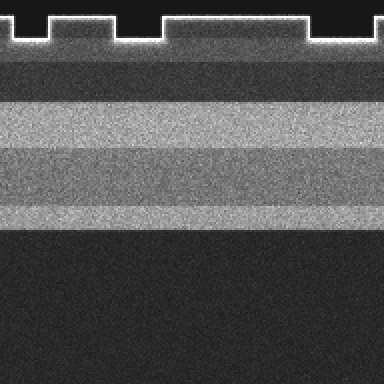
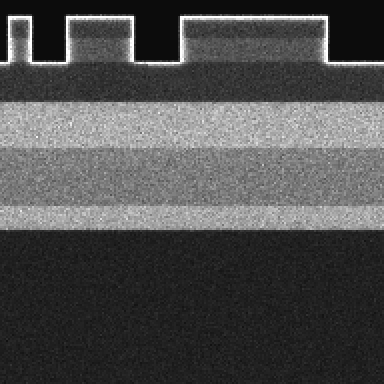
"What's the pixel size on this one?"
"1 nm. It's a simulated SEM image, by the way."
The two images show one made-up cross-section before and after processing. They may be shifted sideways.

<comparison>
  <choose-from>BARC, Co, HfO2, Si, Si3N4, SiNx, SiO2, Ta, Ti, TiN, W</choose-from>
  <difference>SiO2 removed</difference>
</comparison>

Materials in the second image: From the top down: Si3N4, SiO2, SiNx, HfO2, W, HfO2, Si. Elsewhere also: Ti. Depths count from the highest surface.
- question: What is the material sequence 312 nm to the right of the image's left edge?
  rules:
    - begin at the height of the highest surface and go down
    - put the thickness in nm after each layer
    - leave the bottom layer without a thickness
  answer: Si3N4 22, SiO2 24, SiNx 40, HfO2 46, W 58, HfO2 24, Si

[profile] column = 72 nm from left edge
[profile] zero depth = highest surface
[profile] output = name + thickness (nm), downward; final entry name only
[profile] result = Si3N4 22, SiO2 24, SiNx 40, HfO2 46, W 58, HfO2 24, Si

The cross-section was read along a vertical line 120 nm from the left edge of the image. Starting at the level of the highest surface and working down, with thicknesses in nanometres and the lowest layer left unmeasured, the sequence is Si3N4 22, SiO2 24, Ti 40, HfO2 46, W 58, HfO2 24, Si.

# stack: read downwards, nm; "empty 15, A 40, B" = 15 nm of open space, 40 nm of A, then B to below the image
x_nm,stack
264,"Si3N4 22, SiO2 24, SiNx 40, HfO2 46, W 58, HfO2 24, Si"